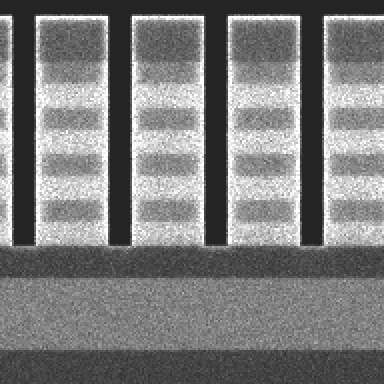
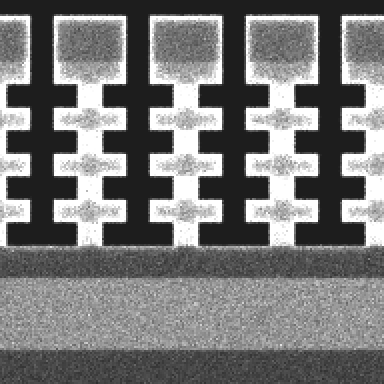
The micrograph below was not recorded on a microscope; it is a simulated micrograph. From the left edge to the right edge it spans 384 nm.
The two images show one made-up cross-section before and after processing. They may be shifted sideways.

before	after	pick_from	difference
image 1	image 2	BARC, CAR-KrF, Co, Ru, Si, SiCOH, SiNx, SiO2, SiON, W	Ru removed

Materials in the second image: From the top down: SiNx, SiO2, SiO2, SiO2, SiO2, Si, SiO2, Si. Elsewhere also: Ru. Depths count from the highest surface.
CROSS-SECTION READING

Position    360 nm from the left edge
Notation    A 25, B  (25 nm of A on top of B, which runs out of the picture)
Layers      SiNx 46, SiO2 22, empty 24, SiO2 22, empty 24, SiO2 22, empty 24, SiO2 22, empty 24, Si 32, SiO2 72, Si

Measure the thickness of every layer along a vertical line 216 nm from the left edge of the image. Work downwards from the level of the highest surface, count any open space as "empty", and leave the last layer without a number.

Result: SiNx 46, SiO2 22, empty 24, SiO2 22, empty 24, SiO2 22, empty 24, SiO2 22, empty 24, Si 32, SiO2 72, Si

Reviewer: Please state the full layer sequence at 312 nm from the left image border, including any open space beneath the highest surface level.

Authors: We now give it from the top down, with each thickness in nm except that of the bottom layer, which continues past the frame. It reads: SiNx 46, SiO2 22, empty 24, SiO2 22, empty 24, SiO2 22, empty 24, SiO2 22, empty 24, Si 32, SiO2 72, Si